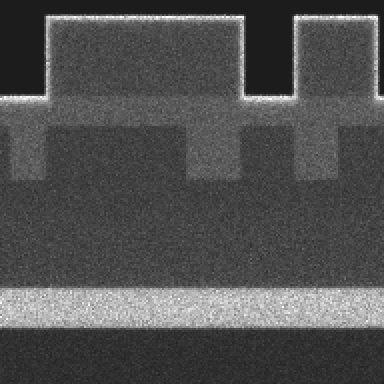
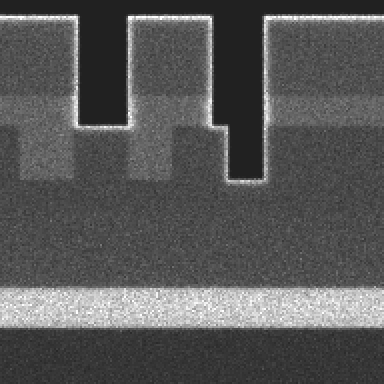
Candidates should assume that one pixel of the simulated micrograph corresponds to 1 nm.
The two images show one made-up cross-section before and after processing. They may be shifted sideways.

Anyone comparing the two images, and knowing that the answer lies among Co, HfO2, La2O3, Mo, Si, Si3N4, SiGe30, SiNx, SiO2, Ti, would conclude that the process removed SiO2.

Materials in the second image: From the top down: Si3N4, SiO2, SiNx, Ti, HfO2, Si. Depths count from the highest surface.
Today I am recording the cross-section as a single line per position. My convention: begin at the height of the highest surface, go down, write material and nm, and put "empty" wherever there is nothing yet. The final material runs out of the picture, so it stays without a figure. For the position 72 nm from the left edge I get Si3N4 80, SiO2 84, SiNx 32, Ti 76, HfO2 40, Si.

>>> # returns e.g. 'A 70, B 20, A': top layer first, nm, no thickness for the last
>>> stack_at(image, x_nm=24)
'Si3N4 80, SiO2 84, SiNx 32, Ti 76, HfO2 40, Si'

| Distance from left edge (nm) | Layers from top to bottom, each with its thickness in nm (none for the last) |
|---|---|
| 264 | Si3N4 80, SiO2 30, SiNx 86, Ti 76, HfO2 40, Si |